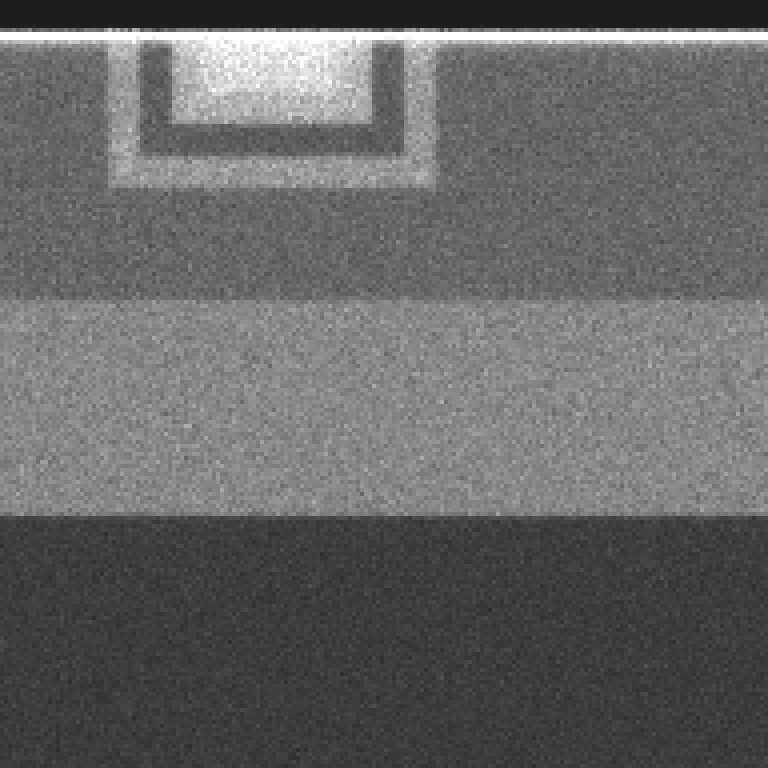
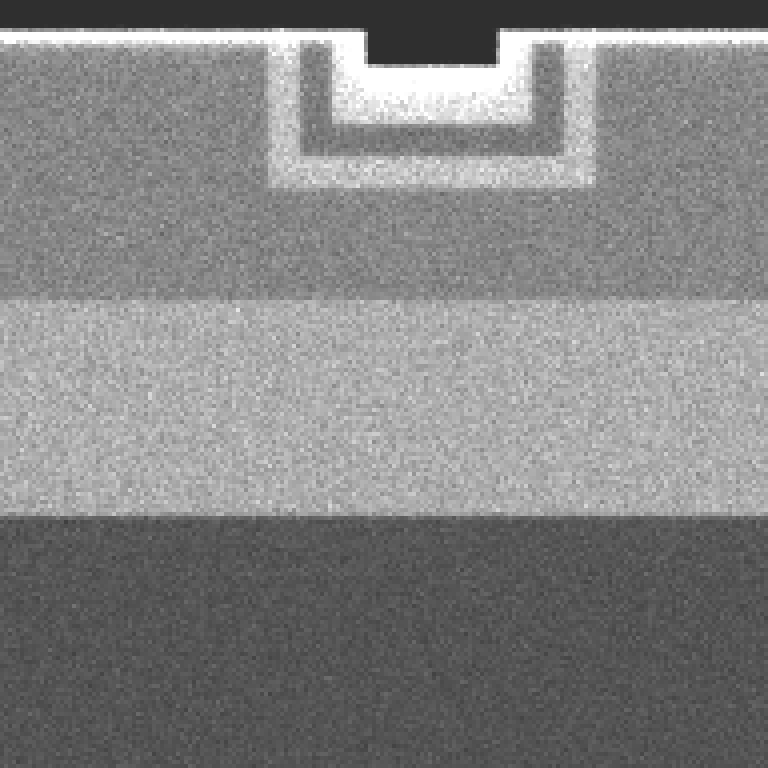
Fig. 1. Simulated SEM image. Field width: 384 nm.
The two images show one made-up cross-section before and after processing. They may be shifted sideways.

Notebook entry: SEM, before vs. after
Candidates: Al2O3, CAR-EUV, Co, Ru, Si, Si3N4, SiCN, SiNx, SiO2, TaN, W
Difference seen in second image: W removed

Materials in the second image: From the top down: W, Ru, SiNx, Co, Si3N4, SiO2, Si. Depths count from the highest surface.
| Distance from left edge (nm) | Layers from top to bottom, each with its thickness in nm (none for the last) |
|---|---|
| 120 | Si3N4 134, SiO2 108, Si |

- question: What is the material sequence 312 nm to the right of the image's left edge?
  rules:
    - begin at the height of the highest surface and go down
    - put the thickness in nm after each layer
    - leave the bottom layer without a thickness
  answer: Si3N4 134, SiO2 108, Si